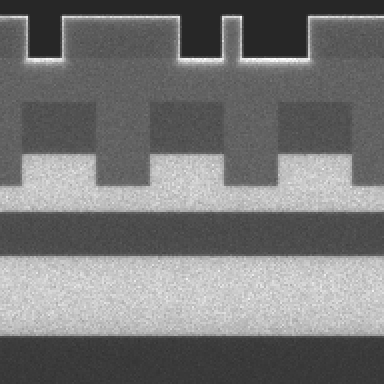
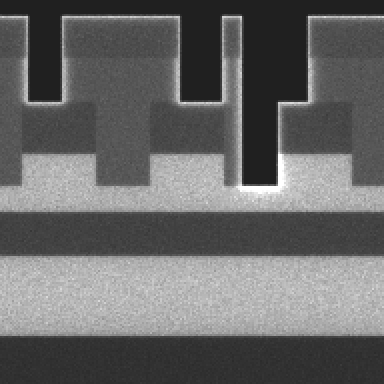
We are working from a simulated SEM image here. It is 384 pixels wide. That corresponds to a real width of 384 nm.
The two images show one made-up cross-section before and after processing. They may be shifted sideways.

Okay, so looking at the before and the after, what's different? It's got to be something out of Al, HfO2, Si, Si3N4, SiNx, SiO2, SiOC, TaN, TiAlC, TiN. SiO2, removed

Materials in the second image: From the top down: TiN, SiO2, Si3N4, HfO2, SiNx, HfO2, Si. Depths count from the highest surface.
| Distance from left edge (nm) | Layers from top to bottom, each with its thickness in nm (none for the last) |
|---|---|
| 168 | TiN 42, SiO2 44, Si3N4 52, HfO2 58, SiNx 44, HfO2 80, Si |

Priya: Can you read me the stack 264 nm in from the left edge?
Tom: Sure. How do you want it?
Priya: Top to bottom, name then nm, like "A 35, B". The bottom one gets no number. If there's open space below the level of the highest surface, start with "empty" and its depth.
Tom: empty 170, HfO2 26, SiNx 44, HfO2 80, Si